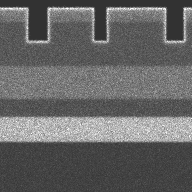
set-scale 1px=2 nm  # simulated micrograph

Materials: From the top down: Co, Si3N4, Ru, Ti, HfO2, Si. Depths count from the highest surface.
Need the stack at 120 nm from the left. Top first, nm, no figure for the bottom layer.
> Co 28, Si3N4 88, Ru 66, Ti 36, HfO2 50, Si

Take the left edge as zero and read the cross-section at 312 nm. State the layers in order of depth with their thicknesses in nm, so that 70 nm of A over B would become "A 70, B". Co 28, Si3N4 88, Ru 66, Ti 36, HfO2 50, Si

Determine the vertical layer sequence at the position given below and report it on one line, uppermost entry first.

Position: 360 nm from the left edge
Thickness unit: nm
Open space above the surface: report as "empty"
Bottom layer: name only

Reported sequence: empty 66, Si3N4 50, Ru 66, Ti 36, HfO2 50, Si